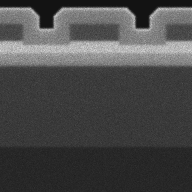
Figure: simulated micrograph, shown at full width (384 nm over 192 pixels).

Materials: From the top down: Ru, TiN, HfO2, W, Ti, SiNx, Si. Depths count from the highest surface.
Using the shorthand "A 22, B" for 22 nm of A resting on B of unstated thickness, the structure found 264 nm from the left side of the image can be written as empty 12, Ru 62, HfO2 16, W 26, Ti 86, SiNx 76, Si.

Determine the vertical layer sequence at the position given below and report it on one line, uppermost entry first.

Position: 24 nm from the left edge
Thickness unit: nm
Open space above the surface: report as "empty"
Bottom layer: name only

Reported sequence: Ru 32, TiN 34, HfO2 24, W 26, Ti 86, SiNx 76, Si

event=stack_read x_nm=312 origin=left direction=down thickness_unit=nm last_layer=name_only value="empty 4, Ru 70, HfO2 16, W 26, Ti 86, SiNx 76, Si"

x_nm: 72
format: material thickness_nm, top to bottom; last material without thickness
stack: empty 12, Ru 62, HfO2 16, W 26, Ti 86, SiNx 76, Si